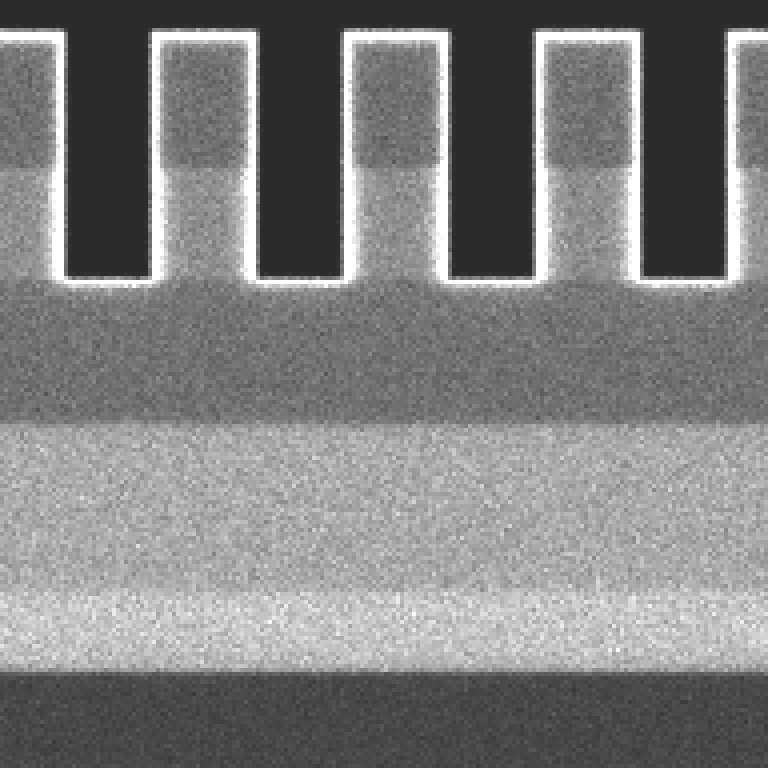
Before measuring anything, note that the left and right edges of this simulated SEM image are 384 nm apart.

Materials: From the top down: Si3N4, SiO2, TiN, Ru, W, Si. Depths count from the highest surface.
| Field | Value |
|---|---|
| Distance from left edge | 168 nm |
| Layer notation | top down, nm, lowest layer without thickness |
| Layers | empty 124, TiN 72, Ru 84, W 40, Si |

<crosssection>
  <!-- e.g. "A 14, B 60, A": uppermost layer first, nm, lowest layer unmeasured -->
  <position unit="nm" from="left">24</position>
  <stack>Si3N4 68, SiO2 56, TiN 72, Ru 84, W 40, Si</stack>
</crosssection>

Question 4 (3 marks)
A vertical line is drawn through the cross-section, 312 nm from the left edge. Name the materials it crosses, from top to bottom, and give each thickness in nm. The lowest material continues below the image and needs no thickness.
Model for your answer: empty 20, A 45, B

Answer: Si3N4 68, SiO2 56, TiN 72, Ru 84, W 40, Si